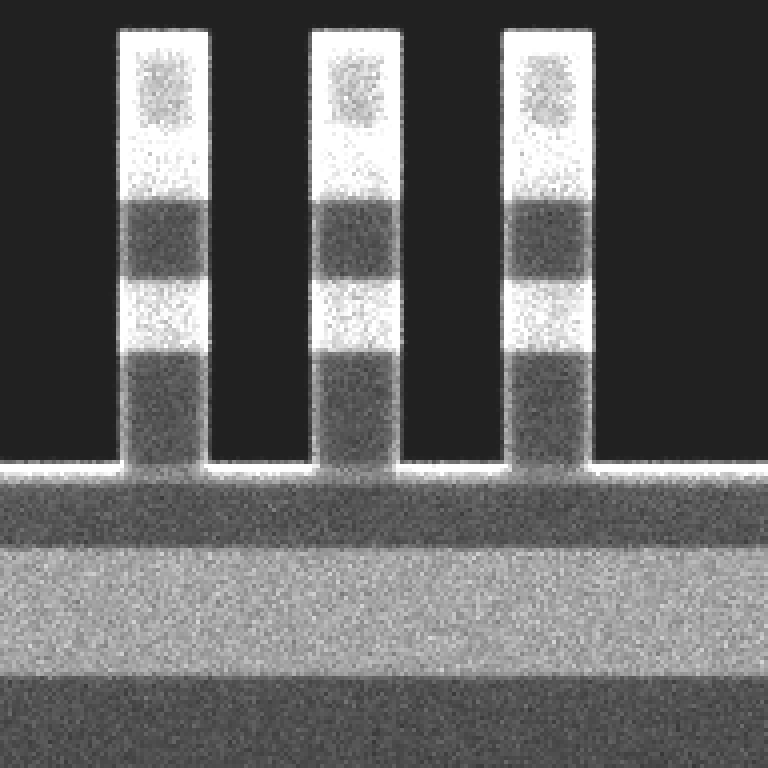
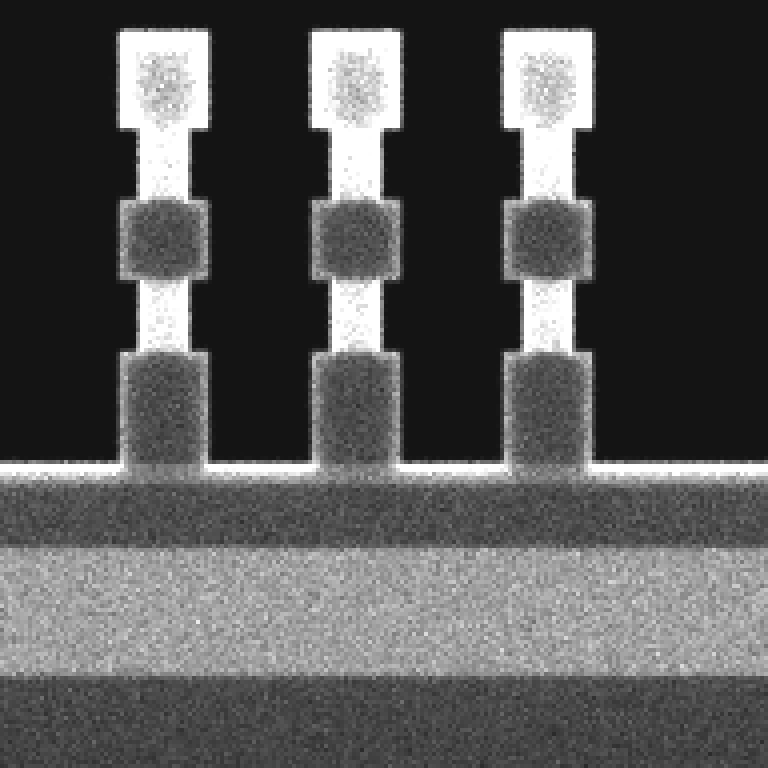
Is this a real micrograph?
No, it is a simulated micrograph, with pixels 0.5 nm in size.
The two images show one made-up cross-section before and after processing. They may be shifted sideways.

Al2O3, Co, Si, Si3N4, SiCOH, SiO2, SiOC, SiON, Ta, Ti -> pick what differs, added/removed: Co removed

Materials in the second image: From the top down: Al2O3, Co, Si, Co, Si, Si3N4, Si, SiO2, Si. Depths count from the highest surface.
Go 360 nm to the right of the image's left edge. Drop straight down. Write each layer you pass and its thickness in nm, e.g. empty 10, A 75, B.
empty 216, Si3N4 10, Si 32, SiO2 64, Si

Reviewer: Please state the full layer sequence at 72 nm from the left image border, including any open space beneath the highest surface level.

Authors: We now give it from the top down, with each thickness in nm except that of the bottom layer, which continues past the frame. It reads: Al2O3 48, Co 36, Si 40, Co 36, Si 56, Si3N4 10, Si 32, SiO2 64, Si